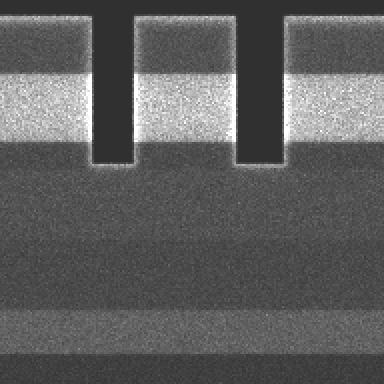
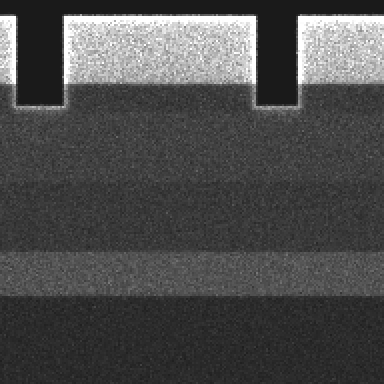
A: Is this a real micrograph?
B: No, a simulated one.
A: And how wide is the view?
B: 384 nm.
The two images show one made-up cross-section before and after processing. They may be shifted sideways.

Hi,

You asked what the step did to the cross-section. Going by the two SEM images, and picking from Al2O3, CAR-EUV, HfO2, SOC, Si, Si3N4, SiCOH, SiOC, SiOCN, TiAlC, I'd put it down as SOC, removed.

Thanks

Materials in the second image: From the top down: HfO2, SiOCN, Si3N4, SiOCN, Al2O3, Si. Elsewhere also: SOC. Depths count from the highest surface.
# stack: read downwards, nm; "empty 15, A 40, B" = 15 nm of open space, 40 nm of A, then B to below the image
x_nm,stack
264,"empty 90, SiOCN 6, Si3N4 70, SiOCN 70, Al2O3 44, Si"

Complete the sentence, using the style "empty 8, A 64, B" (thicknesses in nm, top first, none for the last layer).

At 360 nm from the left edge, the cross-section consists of HfO2 68, SiOCN 28, Si3N4 70, SiOCN 70, Al2O3 44, Si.